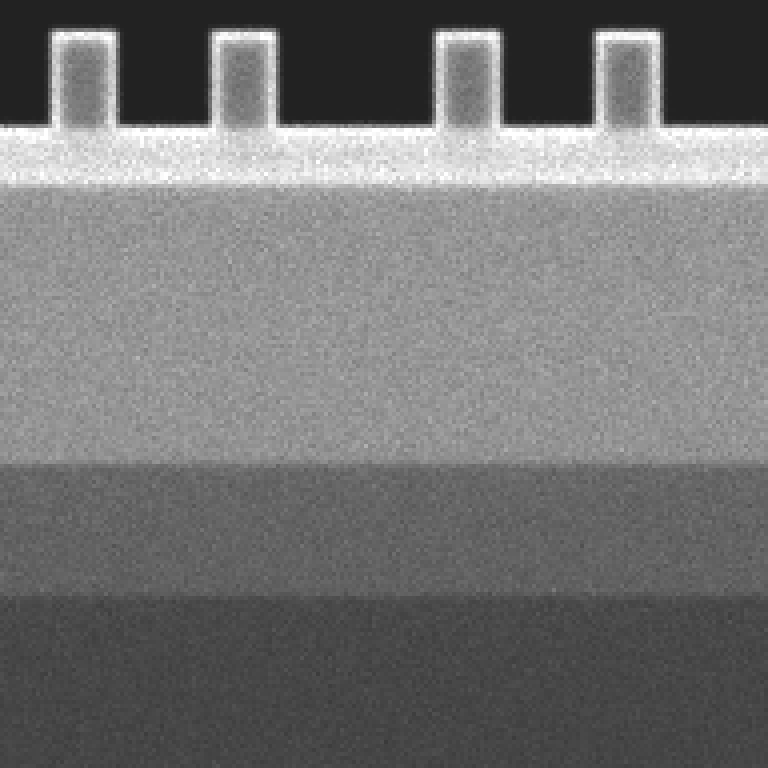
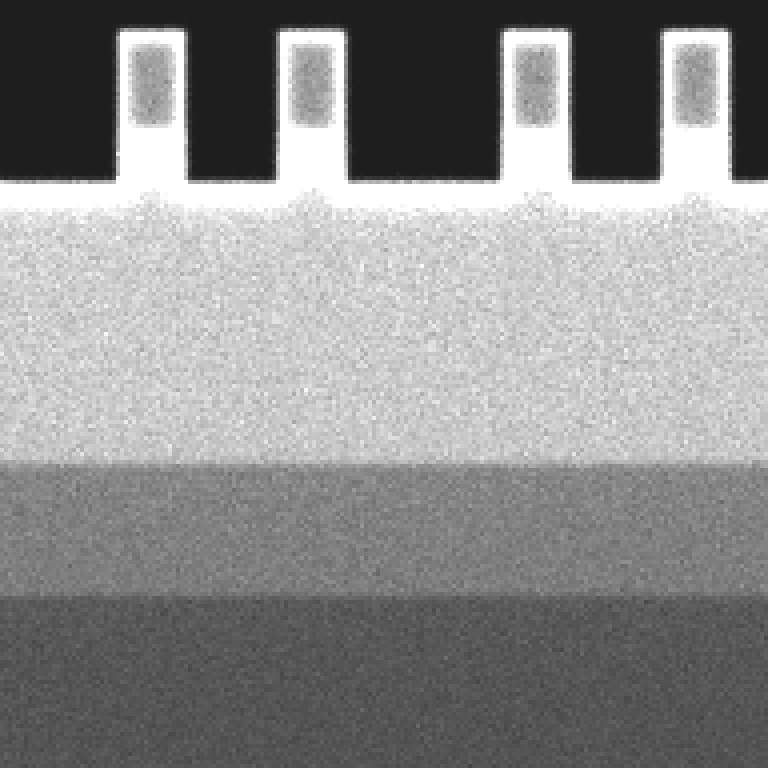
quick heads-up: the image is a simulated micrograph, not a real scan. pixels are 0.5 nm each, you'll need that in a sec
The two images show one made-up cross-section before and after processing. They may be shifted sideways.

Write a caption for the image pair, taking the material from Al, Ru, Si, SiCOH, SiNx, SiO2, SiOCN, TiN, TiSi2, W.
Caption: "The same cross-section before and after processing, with W removed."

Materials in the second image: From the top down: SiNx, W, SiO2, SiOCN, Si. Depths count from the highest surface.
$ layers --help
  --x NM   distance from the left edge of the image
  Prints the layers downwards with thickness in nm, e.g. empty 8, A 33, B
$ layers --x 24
empty 76, SiO2 140, SiOCN 66, Si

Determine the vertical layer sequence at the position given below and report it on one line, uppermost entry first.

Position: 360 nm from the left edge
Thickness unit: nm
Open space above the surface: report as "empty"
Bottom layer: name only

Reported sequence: SiNx 48, W 28, SiO2 140, SiOCN 66, Si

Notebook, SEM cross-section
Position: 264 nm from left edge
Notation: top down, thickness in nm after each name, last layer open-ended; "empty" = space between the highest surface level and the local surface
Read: SiNx 48, W 28, SiO2 140, SiOCN 66, Si